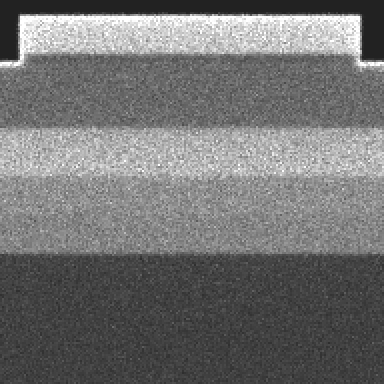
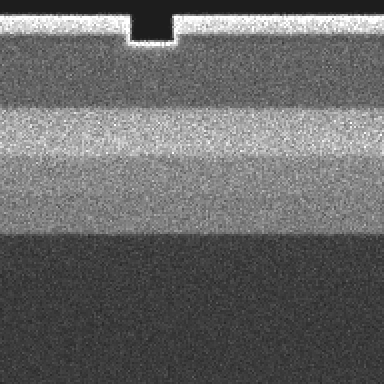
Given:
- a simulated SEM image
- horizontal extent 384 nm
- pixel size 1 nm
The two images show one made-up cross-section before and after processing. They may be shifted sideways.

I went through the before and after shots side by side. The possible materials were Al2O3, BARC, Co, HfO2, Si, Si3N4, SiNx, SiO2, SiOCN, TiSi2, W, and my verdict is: removed, W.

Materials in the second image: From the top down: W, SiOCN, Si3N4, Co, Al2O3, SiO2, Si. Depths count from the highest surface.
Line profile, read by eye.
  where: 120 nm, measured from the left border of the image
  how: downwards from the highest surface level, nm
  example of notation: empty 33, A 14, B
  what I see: W 18, SiOCN 8, Si3N4 66, Co 48, Al2O3 38, SiO2 40, Si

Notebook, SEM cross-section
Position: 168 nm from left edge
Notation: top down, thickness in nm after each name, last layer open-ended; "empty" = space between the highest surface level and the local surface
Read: empty 26, Si3N4 66, Co 48, Al2O3 38, SiO2 40, Si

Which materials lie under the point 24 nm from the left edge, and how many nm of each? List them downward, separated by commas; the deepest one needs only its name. W 18, SiOCN 8, Si3N4 66, Co 48, Al2O3 38, SiO2 40, Si